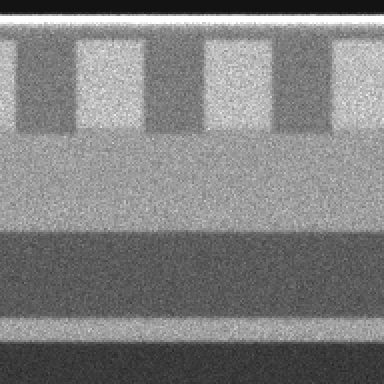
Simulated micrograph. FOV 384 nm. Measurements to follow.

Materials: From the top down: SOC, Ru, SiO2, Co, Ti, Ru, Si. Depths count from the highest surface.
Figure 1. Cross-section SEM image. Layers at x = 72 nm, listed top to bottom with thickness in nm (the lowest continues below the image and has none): SOC 118, SiO2 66, Co 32, Ti 86, Ru 24, Si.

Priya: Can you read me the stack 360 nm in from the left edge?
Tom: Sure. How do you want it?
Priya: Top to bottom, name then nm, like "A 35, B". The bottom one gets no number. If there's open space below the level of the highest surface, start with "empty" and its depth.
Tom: SOC 24, Ru 88, SiO2 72, Co 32, Ti 86, Ru 24, Si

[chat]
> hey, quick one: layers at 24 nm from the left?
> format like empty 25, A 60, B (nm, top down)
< SOC 118, SiO2 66, Co 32, Ti 86, Ru 24, Si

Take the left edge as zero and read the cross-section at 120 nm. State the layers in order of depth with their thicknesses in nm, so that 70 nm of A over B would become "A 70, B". SOC 24, Ru 88, SiO2 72, Co 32, Ti 86, Ru 24, Si